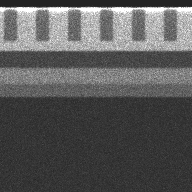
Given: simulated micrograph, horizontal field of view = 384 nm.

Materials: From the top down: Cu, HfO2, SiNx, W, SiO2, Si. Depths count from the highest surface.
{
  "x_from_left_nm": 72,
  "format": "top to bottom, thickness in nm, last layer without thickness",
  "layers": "Cu 66, HfO2 20, SiNx 34, W 32, SiO2 26, Si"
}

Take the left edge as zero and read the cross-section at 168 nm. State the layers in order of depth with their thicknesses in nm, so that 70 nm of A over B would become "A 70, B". HfO2 86, SiNx 34, W 32, SiO2 26, Si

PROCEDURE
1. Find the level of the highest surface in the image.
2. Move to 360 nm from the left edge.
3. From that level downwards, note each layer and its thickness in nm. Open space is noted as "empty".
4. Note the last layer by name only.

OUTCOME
HfO2 86, SiNx 34, W 32, SiO2 26, Si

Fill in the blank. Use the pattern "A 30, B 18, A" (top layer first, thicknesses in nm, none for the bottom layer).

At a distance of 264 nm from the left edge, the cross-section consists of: Cu 66, HfO2 20, SiNx 34, W 32, SiO2 26, Si